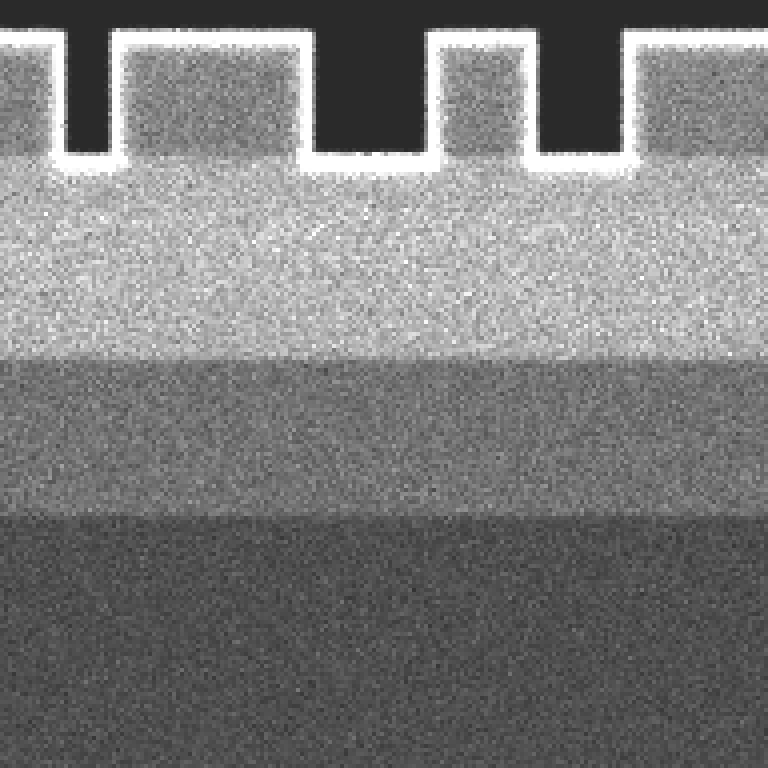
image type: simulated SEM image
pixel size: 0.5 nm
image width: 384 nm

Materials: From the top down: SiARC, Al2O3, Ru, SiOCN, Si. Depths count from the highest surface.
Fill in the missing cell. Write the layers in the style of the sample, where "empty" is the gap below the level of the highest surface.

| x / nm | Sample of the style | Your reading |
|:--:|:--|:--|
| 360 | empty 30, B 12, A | SiARC 62, Al2O3 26, Ru 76, SiOCN 78, Si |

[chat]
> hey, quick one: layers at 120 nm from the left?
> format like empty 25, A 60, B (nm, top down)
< SiARC 62, Al2O3 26, Ru 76, SiOCN 78, Si